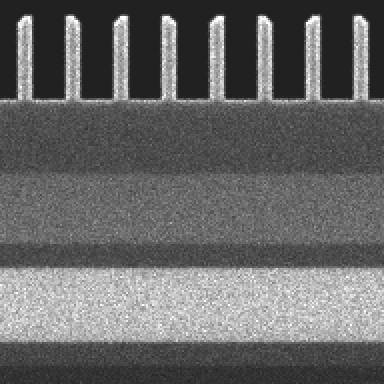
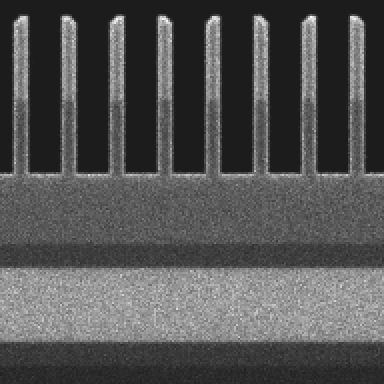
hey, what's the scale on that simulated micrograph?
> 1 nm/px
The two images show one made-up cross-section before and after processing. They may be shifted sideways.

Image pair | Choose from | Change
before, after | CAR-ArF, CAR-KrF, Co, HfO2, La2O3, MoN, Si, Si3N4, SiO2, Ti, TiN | TiN (removed)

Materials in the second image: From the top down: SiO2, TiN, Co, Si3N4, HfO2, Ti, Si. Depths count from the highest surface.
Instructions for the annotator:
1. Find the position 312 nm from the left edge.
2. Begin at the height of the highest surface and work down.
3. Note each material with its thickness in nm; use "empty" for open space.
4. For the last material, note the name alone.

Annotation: SiO2 84, TiN 74, Co 70, Si3N4 24, HfO2 74, Ti 24, Si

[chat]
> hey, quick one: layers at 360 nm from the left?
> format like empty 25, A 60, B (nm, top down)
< empty 4, SiO2 80, TiN 74, Co 70, Si3N4 24, HfO2 74, Ti 24, Si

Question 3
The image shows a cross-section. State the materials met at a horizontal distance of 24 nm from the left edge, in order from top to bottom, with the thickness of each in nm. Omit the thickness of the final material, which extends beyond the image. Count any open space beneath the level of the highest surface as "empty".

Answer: SiO2 84, TiN 74, Co 70, Si3N4 24, HfO2 74, Ti 24, Si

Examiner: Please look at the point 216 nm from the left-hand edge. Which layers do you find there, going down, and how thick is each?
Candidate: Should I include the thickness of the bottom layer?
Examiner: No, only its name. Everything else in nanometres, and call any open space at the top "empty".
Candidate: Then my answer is SiO2 84, TiN 74, Co 70, Si3N4 24, HfO2 74, Ti 24, Si